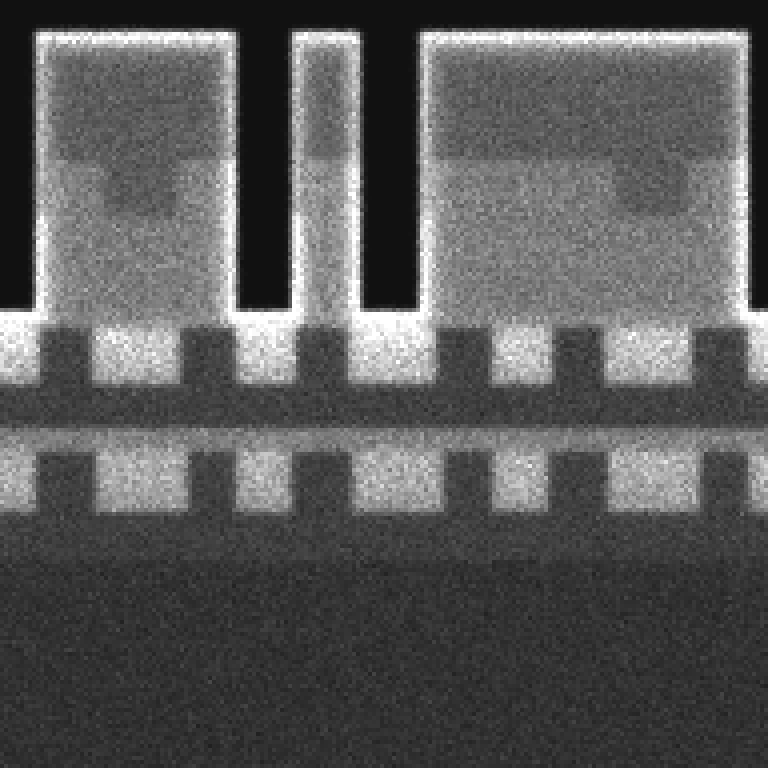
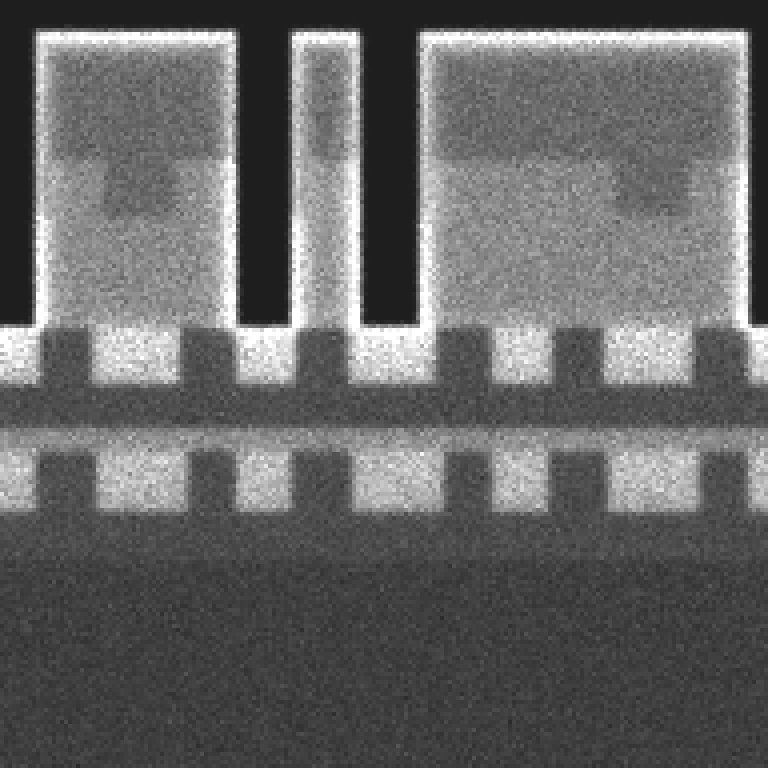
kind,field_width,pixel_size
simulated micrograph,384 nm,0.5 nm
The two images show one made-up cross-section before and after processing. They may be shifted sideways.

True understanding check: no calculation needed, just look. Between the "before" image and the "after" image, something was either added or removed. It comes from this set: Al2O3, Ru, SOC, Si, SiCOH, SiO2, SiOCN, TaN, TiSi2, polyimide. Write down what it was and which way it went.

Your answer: Al2O3 (removed)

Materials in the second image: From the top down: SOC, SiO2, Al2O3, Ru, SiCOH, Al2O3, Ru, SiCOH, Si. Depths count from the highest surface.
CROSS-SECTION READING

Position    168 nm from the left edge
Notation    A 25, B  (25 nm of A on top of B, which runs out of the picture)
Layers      SOC 64, SiO2 76, Al2O3 8, SiCOH 50, Al2O3 12, SiCOH 54, Si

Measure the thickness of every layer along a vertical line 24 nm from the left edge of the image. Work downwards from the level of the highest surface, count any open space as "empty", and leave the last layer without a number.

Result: SOC 92, SiO2 48, Al2O3 8, SiCOH 50, Al2O3 12, SiCOH 54, Si